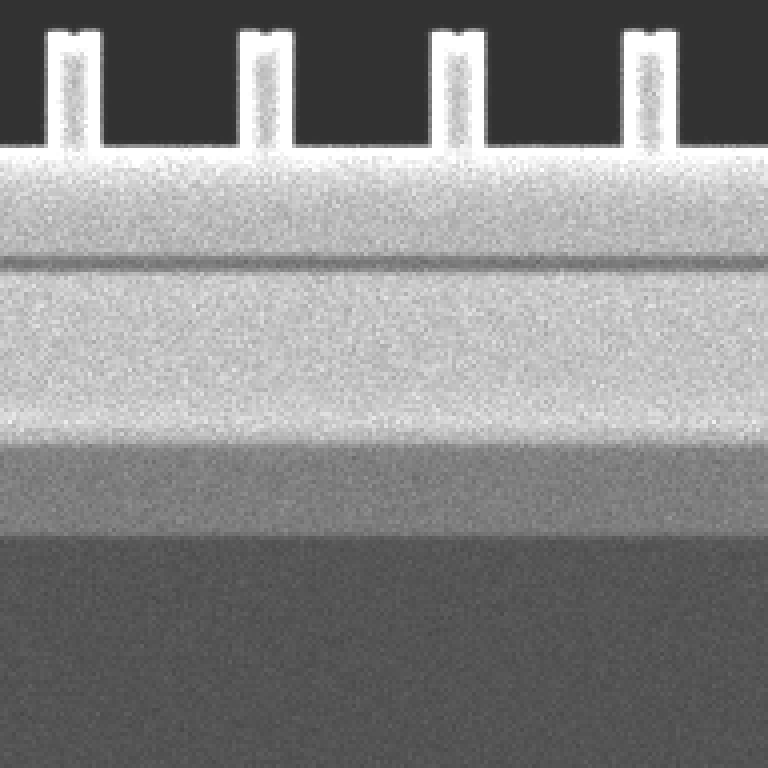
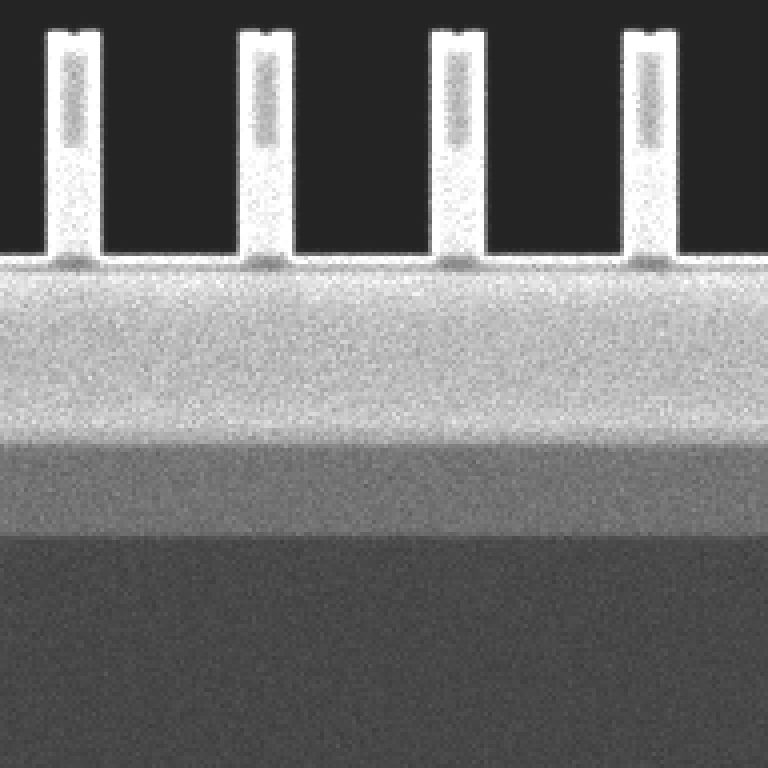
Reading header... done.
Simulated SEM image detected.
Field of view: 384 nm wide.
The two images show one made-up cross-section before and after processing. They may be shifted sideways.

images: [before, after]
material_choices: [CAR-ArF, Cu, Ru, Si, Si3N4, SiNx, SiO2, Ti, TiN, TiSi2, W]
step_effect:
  removed: Ru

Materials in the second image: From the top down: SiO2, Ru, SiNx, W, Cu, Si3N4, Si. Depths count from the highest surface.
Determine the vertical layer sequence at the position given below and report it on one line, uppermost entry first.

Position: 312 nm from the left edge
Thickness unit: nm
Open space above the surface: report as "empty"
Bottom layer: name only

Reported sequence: SiO2 58, Ru 54, SiNx 8, W 78, Cu 8, Si3N4 46, Si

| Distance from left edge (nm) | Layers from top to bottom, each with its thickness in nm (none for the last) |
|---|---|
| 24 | SiO2 58, Ru 54, SiNx 8, W 78, Cu 8, Si3N4 46, Si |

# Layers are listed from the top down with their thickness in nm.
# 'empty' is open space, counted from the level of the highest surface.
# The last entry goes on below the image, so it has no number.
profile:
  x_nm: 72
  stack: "empty 112, SiNx 8, W 78, Cu 8, Si3N4 46, Si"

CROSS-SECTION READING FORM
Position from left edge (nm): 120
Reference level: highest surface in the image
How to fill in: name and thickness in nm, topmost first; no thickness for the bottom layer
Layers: SiO2 58, Ru 54, SiNx 8, W 78, Cu 8, Si3N4 46, Si